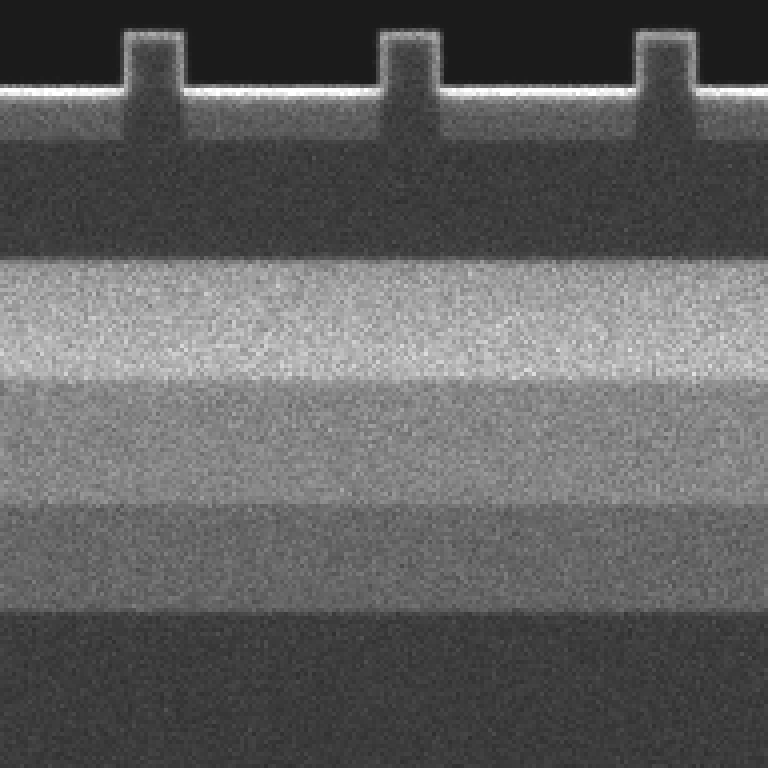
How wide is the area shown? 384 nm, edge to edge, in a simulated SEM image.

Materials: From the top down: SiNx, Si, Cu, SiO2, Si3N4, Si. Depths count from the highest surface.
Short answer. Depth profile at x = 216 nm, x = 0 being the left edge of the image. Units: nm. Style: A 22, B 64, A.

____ Si 114, Cu 60, SiO2 62, Si3N4 54, Si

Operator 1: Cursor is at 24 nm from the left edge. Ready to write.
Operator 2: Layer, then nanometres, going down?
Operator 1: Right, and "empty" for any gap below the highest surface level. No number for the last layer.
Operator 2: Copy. empty 28, SiNx 26, Si 60, Cu 60, SiO2 62, Si3N4 54, Si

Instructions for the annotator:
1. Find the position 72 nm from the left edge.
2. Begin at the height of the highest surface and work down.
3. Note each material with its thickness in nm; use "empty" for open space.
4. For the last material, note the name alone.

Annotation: Si 114, Cu 60, SiO2 62, Si3N4 54, Si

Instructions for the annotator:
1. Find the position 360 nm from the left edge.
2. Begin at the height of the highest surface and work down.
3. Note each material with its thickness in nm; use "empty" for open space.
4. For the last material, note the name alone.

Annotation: empty 28, SiNx 26, Si 60, Cu 60, SiO2 62, Si3N4 54, Si